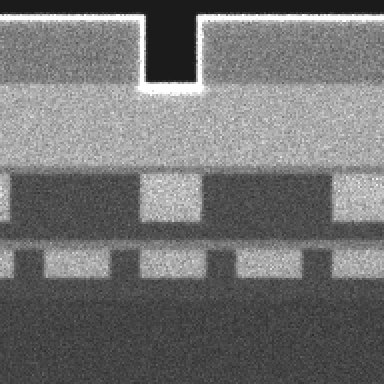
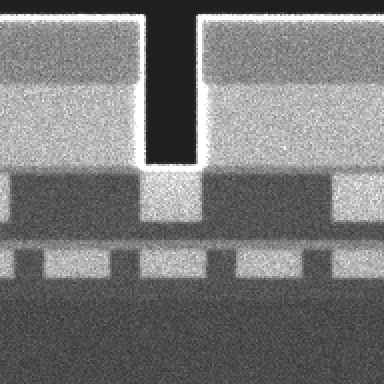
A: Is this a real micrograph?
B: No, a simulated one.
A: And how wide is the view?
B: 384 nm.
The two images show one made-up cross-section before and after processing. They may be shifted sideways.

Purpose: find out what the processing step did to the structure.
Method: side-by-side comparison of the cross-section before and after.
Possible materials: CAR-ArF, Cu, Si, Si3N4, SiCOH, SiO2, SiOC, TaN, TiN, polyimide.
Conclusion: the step removed SiO2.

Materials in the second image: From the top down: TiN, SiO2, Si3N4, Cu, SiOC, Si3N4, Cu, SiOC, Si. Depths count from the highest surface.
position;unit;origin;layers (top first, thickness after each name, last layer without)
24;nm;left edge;TiN 68, SiO2 82, Si3N4 8, SiOC 66, Si3N4 10, SiOC 50, Si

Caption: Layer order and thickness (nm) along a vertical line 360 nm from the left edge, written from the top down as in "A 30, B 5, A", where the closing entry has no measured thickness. TiN 68, SiO2 82, Si3N4 8, Cu 48, SiOC 18, Si3N4 10, Cu 28, SiOC 22, Si